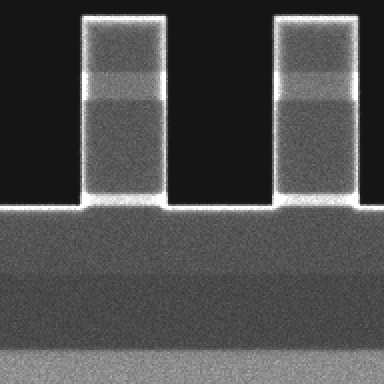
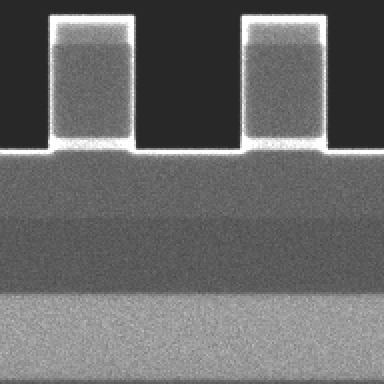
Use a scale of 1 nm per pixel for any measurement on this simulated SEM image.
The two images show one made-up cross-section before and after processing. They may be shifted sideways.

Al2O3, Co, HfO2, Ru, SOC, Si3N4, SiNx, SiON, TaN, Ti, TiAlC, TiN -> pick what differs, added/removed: SOC removed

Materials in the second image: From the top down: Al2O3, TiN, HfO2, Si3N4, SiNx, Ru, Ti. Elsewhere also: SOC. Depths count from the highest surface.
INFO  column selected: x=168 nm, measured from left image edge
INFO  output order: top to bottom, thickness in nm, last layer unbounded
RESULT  empty 134, Si3N4 68, SiNx 76, Ru 86, Ti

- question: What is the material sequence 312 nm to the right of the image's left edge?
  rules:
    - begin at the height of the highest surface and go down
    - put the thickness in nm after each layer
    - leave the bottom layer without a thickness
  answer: Al2O3 28, TiN 94, HfO2 12, Si3N4 68, SiNx 76, Ru 86, Ti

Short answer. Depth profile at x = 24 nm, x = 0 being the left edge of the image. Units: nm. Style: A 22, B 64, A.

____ empty 134, Si3N4 68, SiNx 76, Ru 86, Ti